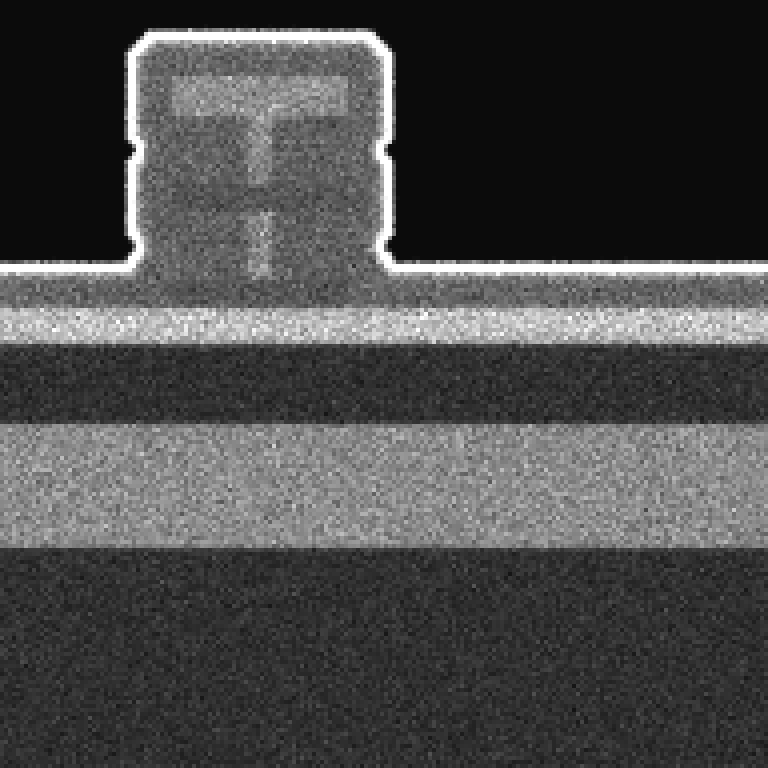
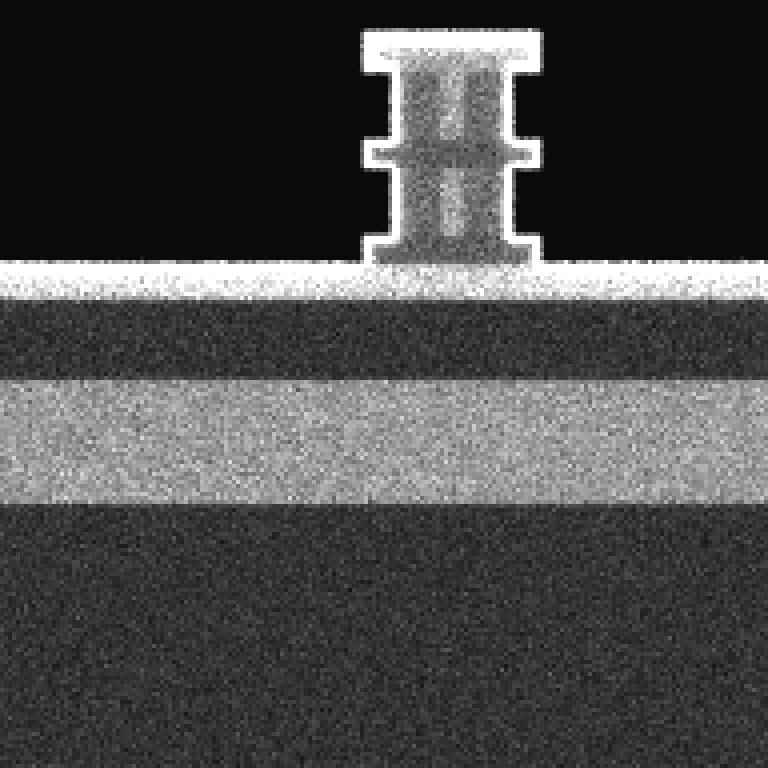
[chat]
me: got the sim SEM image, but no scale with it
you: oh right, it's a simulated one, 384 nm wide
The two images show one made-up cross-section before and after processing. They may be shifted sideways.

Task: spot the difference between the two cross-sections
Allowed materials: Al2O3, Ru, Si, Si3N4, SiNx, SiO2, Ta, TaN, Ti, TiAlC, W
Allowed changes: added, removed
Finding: removed Si3N4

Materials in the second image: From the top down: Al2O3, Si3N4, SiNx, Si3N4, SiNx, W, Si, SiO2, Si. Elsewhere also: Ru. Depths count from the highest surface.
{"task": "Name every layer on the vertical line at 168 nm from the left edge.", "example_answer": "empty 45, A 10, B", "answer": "empty 116, W 18, Si 40, SiO2 62, Si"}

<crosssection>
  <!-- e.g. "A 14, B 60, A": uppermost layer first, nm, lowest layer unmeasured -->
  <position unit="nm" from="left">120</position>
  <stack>empty 116, W 18, Si 40, SiO2 62, Si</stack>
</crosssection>